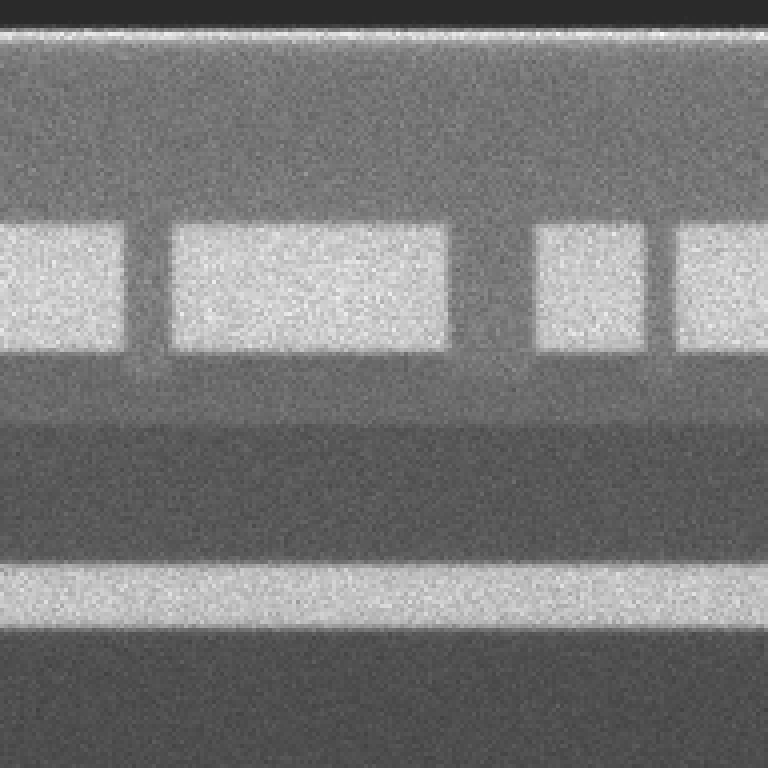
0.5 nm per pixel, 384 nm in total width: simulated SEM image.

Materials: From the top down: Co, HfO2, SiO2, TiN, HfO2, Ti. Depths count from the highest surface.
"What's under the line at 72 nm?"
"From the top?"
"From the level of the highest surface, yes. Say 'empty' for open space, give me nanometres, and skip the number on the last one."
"Co 174, SiO2 22, TiN 70, HfO2 32, Ti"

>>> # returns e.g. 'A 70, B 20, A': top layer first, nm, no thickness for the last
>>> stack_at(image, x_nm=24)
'Co 96, HfO2 64, SiO2 36, TiN 70, HfO2 32, Ti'